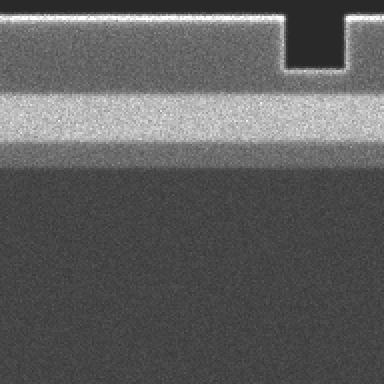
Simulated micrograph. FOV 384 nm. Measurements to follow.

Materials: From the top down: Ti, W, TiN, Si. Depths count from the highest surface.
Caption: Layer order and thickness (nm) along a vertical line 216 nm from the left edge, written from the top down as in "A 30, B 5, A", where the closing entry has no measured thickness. Ti 78, W 48, TiN 26, Si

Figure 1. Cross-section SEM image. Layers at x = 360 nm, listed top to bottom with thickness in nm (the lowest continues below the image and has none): Ti 78, W 48, TiN 26, Si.